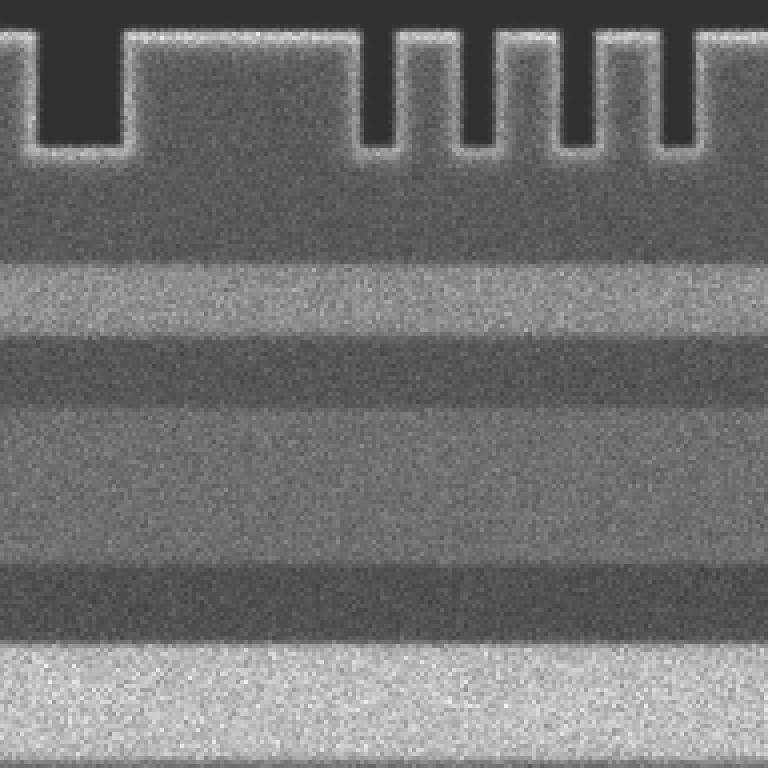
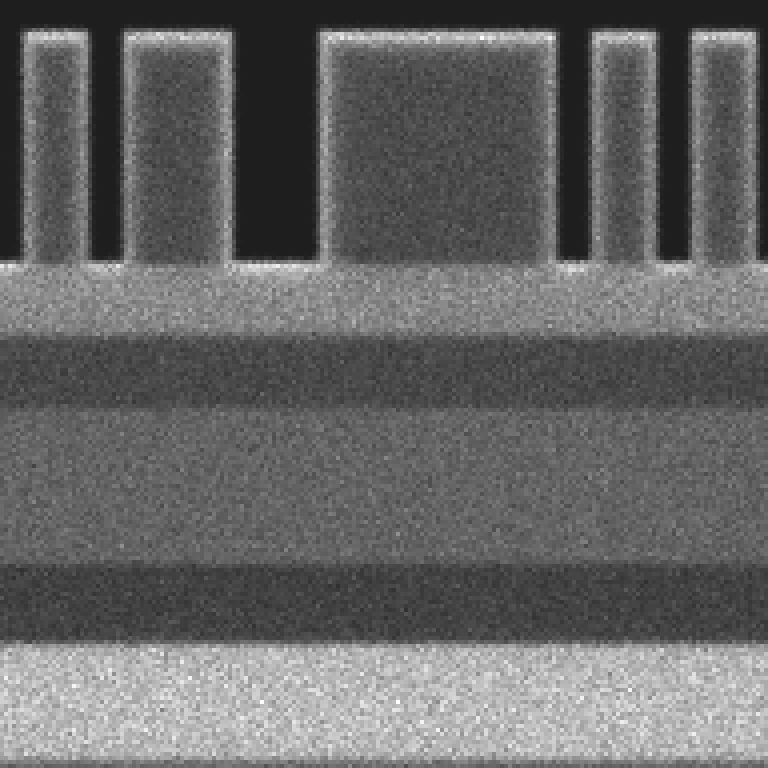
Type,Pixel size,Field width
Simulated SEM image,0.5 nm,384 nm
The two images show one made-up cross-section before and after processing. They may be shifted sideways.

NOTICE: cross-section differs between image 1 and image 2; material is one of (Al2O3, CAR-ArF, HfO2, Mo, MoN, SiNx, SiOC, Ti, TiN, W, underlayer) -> removed: underlayer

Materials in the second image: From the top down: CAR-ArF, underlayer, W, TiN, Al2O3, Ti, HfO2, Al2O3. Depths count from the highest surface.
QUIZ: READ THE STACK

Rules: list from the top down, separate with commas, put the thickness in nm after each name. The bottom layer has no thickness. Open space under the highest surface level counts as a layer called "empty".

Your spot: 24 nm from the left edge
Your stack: CAR-ArF 58, underlayer 58, W 36, TiN 36, Al2O3 78, Ti 40, HfO2 58, Al2O3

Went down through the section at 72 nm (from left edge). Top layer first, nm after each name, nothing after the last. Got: CAR-ArF 58, underlayer 58, W 36, TiN 36, Al2O3 78, Ti 40, HfO2 58, Al2O3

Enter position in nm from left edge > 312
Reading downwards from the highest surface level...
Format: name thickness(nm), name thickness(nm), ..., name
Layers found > CAR-ArF 58, underlayer 58, W 36, TiN 36, Al2O3 78, Ti 40, HfO2 58, Al2O3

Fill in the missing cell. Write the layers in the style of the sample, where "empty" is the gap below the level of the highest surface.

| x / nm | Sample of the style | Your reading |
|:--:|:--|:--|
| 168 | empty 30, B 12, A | CAR-ArF 58, underlayer 58, W 36, TiN 36, Al2O3 78, Ti 40, HfO2 58, Al2O3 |